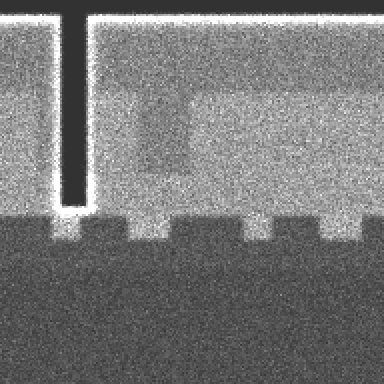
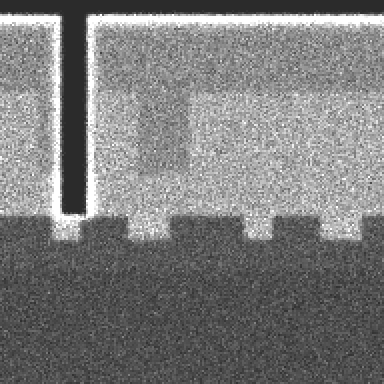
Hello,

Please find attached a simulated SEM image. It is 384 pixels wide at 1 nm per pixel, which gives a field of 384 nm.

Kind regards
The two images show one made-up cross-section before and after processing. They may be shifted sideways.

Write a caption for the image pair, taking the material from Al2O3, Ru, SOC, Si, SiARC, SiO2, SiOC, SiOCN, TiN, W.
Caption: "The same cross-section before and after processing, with Al2O3 removed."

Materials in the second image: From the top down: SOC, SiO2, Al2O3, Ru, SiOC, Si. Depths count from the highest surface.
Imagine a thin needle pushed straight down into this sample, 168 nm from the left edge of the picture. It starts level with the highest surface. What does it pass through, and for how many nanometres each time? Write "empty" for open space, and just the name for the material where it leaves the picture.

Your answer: SOC 158, SiO2 34, Al2O3 8, Ru 24, SiOC 30, Si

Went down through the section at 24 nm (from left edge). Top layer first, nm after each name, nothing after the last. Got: SOC 76, SiO2 116, Al2O3 8, SiOC 54, Si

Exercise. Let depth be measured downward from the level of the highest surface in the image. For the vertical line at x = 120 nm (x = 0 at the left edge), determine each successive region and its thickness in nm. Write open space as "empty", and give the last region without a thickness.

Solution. SOC 76, SiO2 116, Al2O3 8, SiOC 54, Si